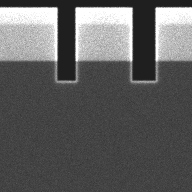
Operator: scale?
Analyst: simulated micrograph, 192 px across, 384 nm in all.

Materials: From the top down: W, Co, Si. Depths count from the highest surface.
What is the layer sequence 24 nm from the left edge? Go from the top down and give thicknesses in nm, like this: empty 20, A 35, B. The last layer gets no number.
W 32, Co 74, Si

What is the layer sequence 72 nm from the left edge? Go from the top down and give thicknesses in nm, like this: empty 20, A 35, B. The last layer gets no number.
W 32, Co 74, Si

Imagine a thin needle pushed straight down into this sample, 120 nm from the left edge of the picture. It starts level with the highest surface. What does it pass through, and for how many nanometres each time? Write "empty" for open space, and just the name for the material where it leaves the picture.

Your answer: empty 146, Si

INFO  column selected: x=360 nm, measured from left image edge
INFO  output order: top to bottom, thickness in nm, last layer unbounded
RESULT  W 32, Co 74, Si